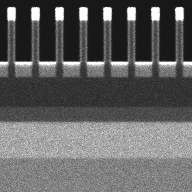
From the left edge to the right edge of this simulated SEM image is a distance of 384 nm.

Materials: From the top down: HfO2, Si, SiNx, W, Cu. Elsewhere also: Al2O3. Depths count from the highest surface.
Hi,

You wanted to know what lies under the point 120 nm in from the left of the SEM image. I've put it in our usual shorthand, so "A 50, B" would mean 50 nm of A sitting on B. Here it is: HfO2 24, Si 174, SiNx 30, W 72, Cu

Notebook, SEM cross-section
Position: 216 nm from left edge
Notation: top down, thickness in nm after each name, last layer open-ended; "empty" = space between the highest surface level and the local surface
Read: HfO2 24, Si 174, SiNx 30, W 72, Cu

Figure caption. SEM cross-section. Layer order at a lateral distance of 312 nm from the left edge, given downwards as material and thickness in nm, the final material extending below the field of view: HfO2 24, Si 174, SiNx 30, W 72, Cu